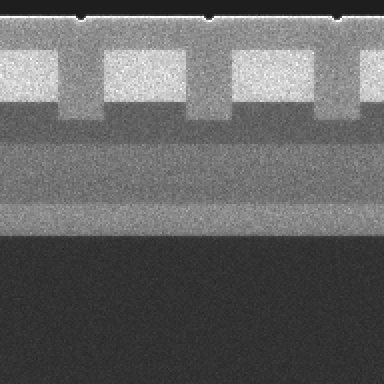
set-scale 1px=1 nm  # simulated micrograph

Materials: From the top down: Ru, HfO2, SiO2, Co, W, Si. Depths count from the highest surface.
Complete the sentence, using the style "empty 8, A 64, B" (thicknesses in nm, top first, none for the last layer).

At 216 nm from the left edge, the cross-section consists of Ru 104, SiO2 24, Co 60, W 32, Si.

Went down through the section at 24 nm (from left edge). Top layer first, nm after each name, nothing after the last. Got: Ru 34, HfO2 52, SiO2 42, Co 60, W 32, Si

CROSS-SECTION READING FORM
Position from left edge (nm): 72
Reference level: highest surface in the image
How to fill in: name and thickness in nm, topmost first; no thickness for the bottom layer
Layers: Ru 104, SiO2 24, Co 60, W 32, Si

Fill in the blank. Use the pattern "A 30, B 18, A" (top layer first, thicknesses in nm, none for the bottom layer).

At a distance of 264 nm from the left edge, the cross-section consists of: Ru 34, HfO2 52, SiO2 42, Co 60, W 32, Si